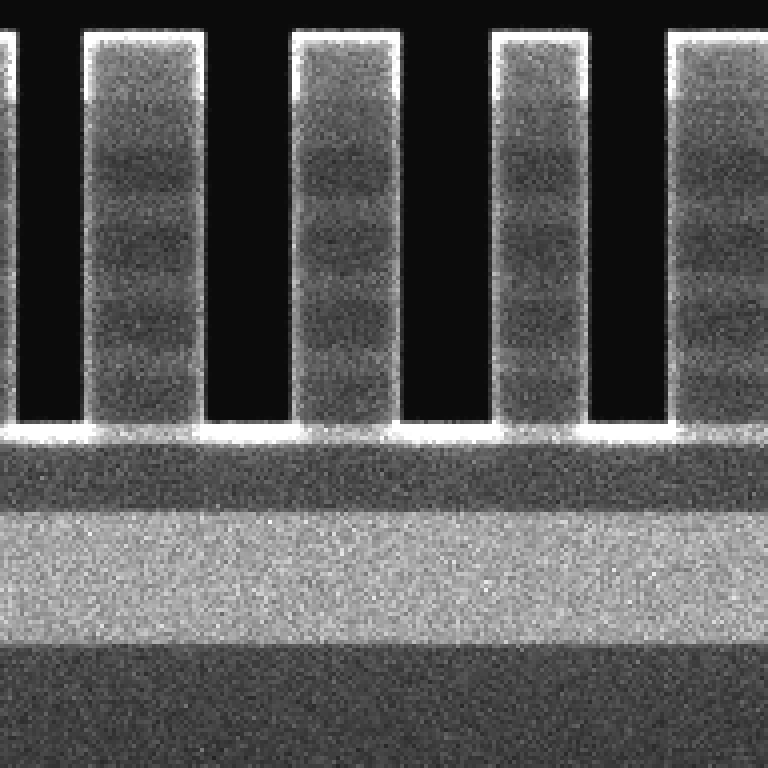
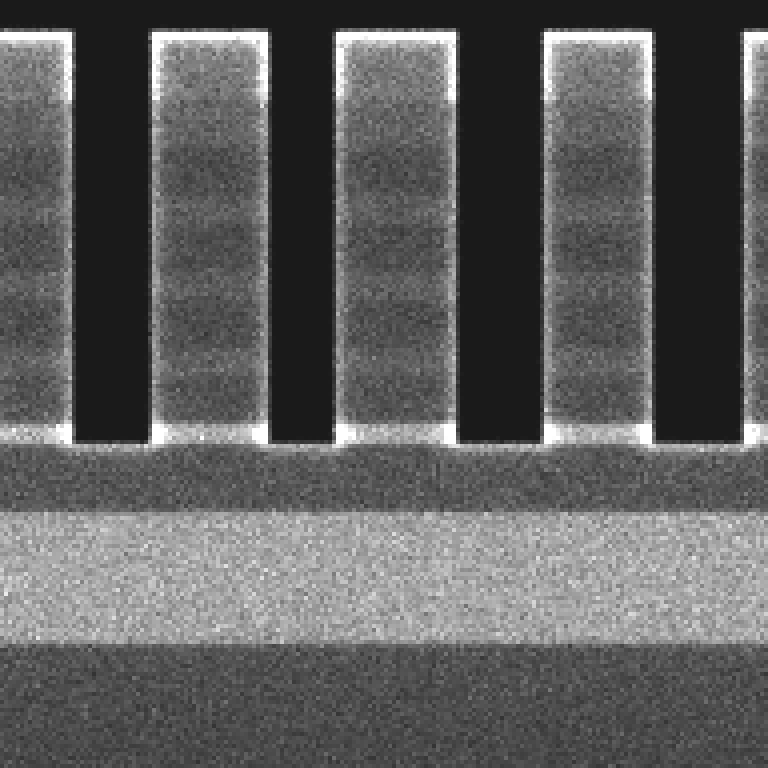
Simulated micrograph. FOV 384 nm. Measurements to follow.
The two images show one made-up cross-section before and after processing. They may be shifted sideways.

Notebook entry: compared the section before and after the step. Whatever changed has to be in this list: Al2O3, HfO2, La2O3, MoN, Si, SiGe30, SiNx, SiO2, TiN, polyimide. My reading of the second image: Al2O3 removed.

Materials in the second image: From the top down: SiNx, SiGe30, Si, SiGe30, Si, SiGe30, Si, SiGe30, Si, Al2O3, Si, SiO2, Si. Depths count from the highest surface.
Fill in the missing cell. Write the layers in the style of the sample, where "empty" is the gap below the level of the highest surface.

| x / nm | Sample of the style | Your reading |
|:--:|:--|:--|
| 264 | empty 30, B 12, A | empty 206, Si 34, SiO2 66, Si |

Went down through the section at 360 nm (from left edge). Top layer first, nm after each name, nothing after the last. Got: empty 206, Si 34, SiO2 66, Si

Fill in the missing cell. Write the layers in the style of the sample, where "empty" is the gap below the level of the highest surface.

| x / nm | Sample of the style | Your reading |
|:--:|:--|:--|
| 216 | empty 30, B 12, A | SiNx 34, SiGe30 24, Si 24, SiGe30 14, Si 24, SiGe30 14, Si 24, SiGe30 14, Si 24, Al2O3 10, Si 34, SiO2 66, Si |